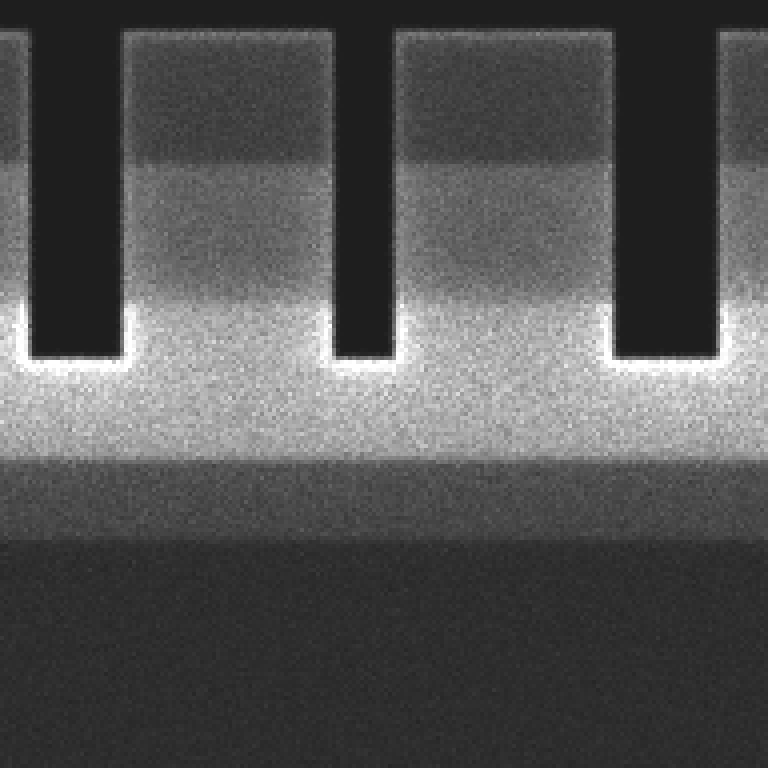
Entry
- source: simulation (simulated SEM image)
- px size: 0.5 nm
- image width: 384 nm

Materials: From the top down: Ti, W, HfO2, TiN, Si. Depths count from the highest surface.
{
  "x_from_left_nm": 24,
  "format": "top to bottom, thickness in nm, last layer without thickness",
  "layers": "empty 164, HfO2 50, TiN 40, Si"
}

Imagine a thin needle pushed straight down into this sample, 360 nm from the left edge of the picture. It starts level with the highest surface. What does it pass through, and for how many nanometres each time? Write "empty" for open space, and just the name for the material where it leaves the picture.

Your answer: Ti 66, W 70, HfO2 78, TiN 40, Si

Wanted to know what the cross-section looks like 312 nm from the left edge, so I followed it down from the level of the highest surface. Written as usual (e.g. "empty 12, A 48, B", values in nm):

empty 164, HfO2 50, TiN 40, Si